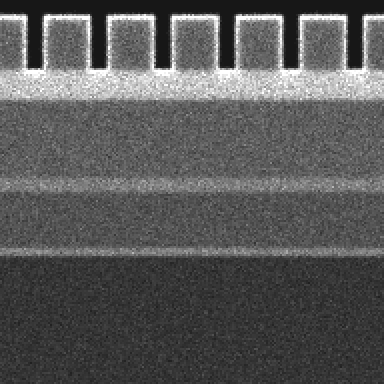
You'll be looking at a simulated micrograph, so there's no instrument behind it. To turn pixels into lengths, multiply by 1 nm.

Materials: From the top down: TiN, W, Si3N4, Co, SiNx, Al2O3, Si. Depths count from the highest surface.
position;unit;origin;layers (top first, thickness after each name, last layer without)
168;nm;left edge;empty 54, W 30, Si3N4 78, Co 14, SiNx 56, Al2O3 8, Si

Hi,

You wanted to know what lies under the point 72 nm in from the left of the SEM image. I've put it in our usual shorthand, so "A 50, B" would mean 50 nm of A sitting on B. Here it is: TiN 54, W 30, Si3N4 78, Co 14, SiNx 56, Al2O3 8, Si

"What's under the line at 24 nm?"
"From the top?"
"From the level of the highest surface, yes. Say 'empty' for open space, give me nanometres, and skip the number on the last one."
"TiN 54, W 30, Si3N4 78, Co 14, SiNx 56, Al2O3 8, Si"